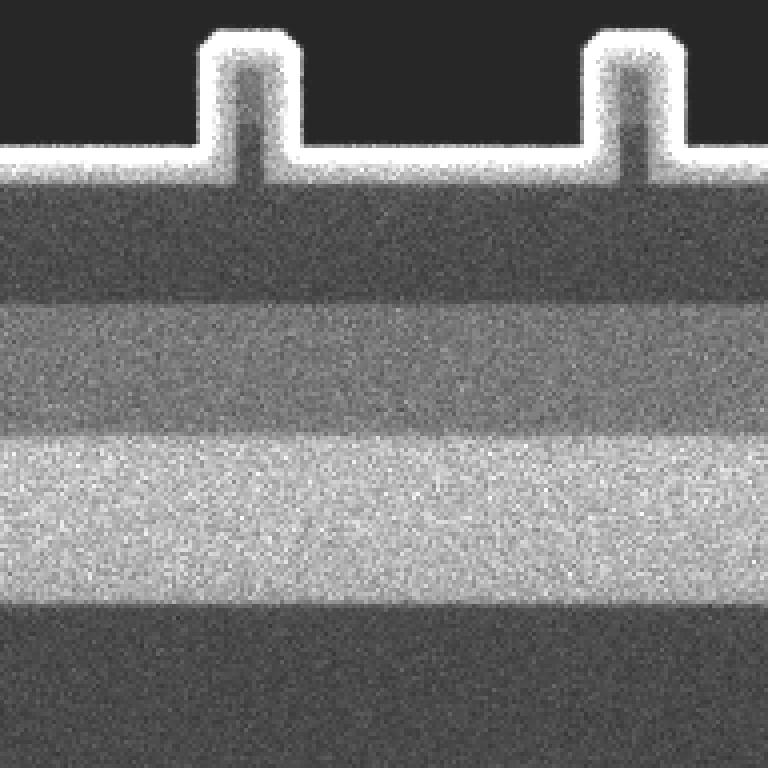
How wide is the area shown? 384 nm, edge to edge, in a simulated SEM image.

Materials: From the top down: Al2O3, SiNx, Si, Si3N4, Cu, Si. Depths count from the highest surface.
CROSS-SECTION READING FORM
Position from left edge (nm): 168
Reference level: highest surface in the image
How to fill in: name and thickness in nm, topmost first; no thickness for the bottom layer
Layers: empty 58, Al2O3 18, Si 60, Si3N4 66, Cu 84, Si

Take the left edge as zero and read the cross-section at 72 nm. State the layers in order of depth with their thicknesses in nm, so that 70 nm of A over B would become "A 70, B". empty 58, Al2O3 18, Si 60, Si3N4 66, Cu 84, Si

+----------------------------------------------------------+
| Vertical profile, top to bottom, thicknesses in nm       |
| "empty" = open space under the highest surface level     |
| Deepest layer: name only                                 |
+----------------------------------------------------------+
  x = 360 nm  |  empty 58, Al2O3 18, Si 60, Si3N4 66, Cu 84, Si